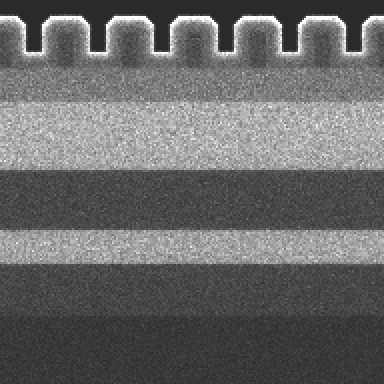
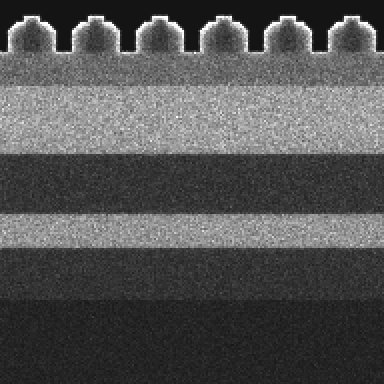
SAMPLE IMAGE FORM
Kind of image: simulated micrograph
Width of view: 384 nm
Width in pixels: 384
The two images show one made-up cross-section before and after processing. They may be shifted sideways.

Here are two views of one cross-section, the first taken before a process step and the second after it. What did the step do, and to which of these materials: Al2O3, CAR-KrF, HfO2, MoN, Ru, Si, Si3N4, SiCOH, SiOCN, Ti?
It removed Al2O3.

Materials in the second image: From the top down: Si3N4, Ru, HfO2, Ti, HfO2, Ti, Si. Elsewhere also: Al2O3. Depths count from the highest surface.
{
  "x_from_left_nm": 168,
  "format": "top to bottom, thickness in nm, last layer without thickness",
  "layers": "empty 6, Al2O3 30, Ru 34, HfO2 68, Ti 60, HfO2 34, Ti 52, Si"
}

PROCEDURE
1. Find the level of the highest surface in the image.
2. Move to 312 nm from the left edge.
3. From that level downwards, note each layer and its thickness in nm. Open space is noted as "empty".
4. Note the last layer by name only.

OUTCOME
empty 36, Ru 34, HfO2 68, Ti 60, HfO2 34, Ti 52, Si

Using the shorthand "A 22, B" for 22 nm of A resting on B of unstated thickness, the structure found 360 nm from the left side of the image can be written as empty 6, Al2O3 30, Ru 34, HfO2 68, Ti 60, HfO2 34, Ti 52, Si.